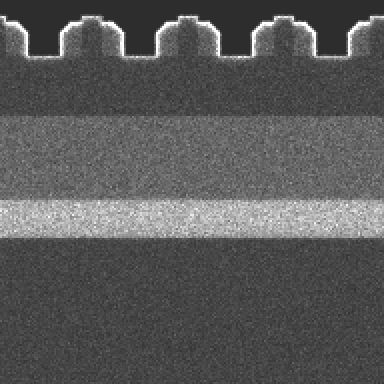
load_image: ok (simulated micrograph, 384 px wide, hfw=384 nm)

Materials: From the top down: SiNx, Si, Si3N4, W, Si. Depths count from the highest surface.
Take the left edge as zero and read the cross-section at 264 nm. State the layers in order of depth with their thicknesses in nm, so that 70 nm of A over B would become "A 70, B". empty 6, SiNx 34, Si 60, Si3N4 84, W 38, Si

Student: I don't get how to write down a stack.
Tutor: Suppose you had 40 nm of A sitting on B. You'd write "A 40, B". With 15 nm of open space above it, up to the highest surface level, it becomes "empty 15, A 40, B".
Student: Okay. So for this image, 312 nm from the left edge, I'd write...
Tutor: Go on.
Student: empty 14, SiNx 26, Si 60, Si3N4 84, W 38, Si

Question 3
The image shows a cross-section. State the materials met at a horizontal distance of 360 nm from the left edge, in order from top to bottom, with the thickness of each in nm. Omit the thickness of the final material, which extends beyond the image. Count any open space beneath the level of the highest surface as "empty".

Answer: empty 6, SiNx 34, Si 60, Si3N4 84, W 38, Si